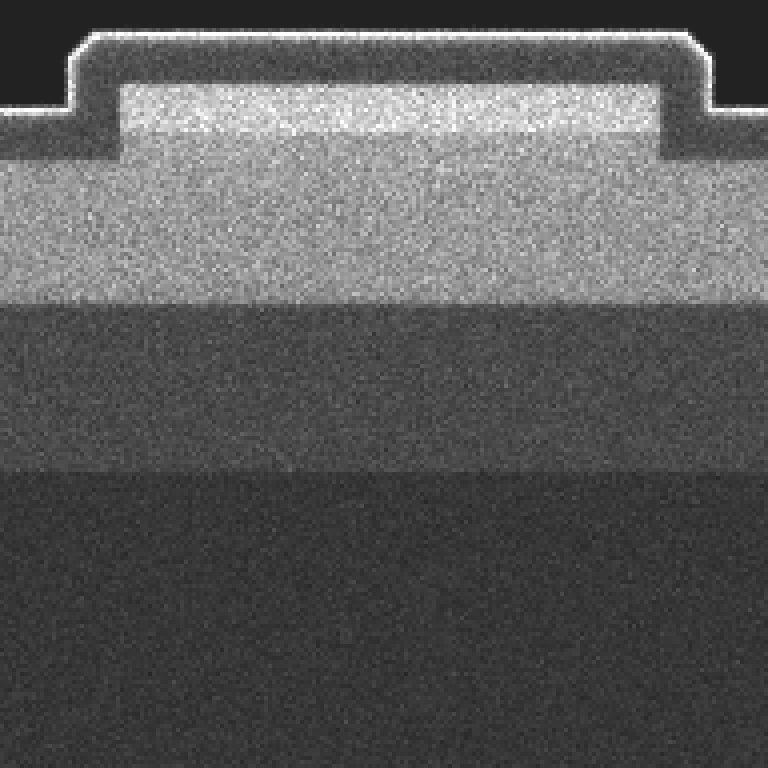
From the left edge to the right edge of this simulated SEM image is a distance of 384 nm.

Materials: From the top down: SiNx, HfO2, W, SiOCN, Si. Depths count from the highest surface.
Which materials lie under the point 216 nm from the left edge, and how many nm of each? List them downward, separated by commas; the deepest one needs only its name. SiNx 26, HfO2 24, W 86, SiOCN 84, Si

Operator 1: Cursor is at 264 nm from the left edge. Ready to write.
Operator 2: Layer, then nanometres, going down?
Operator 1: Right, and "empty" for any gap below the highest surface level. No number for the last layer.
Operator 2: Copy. SiNx 26, HfO2 24, W 86, SiOCN 84, Si